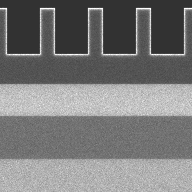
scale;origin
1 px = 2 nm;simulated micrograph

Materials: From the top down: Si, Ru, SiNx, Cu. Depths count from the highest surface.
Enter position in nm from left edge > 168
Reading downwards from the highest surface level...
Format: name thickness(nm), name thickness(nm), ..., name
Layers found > empty 92, Si 60, Ru 64, SiNx 86, Cu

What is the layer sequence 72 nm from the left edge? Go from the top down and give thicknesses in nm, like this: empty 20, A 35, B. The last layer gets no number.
empty 92, Si 60, Ru 64, SiNx 86, Cu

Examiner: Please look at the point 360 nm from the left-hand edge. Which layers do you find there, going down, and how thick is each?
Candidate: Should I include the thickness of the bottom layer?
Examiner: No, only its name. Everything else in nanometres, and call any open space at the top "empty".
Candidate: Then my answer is empty 92, Si 60, Ru 64, SiNx 86, Cu